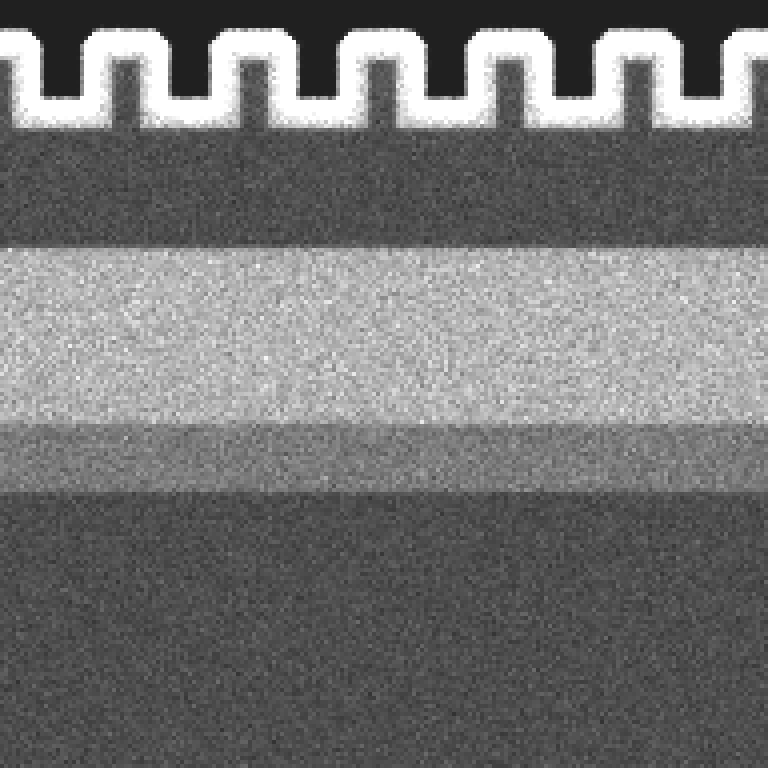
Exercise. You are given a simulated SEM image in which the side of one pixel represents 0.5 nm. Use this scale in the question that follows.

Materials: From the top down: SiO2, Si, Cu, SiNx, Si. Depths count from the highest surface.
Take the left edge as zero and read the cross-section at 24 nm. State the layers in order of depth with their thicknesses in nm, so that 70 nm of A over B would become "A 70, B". empty 34, SiO2 14, Si 60, Cu 88, SiNx 34, Si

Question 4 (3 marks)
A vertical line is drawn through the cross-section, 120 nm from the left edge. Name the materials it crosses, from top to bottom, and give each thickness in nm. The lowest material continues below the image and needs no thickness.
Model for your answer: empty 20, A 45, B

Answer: SiO2 14, Si 94, Cu 88, SiNx 34, Si